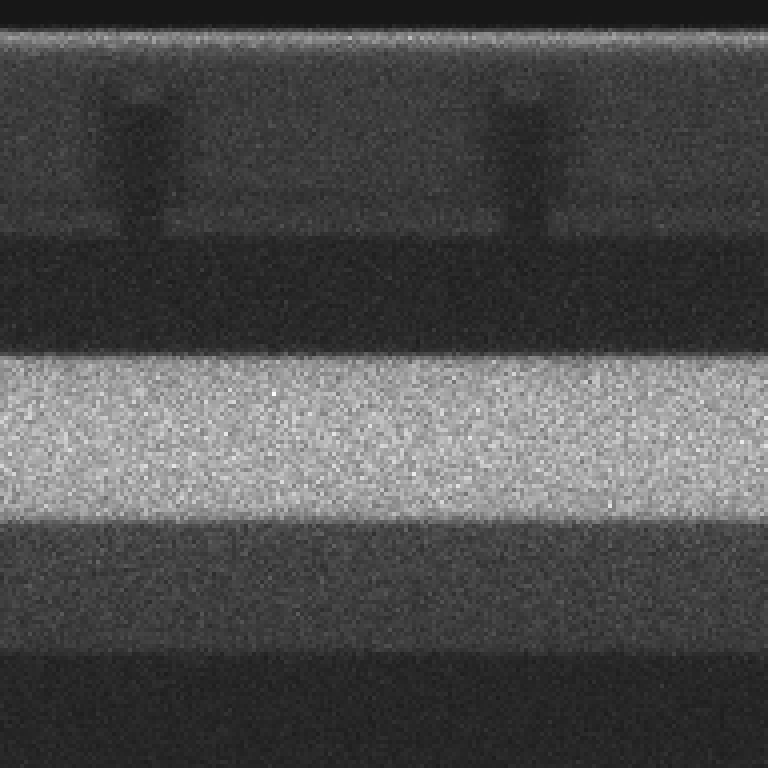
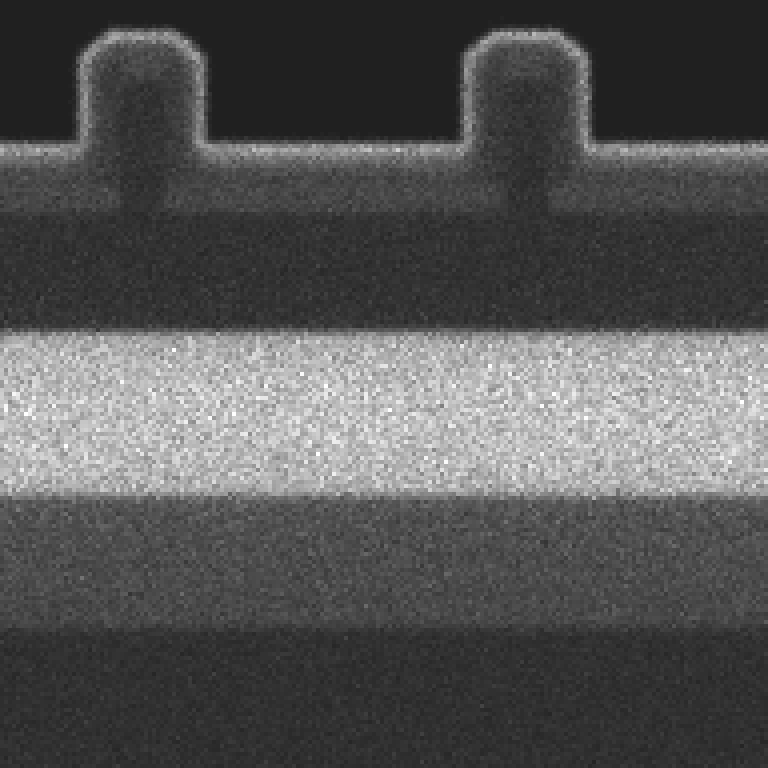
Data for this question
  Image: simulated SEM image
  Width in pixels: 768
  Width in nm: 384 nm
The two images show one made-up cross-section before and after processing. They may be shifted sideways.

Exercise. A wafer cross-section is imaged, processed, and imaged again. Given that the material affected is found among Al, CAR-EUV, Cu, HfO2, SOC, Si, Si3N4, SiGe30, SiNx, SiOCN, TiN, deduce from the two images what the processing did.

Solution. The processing removed SOC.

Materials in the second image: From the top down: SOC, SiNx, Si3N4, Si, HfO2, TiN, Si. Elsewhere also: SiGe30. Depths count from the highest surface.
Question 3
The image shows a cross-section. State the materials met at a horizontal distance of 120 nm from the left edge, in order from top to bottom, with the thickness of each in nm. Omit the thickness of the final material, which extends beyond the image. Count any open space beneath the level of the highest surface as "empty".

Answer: empty 56, SOC 10, SiNx 10, Si3N4 14, Si 60, HfO2 82, TiN 66, Si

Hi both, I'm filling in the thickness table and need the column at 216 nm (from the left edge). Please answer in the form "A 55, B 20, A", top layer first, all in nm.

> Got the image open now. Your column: empty 56, SOC 10, SiNx 10, Si3N4 14, Si 60, HfO2 82, TiN 66, Si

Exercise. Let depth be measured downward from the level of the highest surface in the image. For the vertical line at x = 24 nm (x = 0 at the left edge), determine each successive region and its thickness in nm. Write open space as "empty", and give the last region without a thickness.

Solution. empty 56, SOC 10, SiNx 10, Si3N4 14, Si 60, HfO2 82, TiN 66, Si